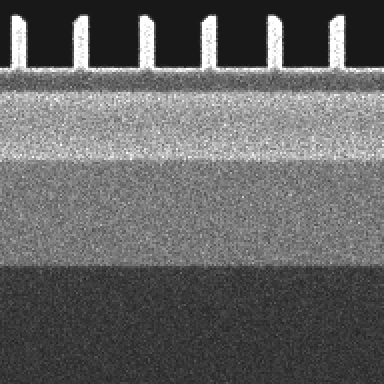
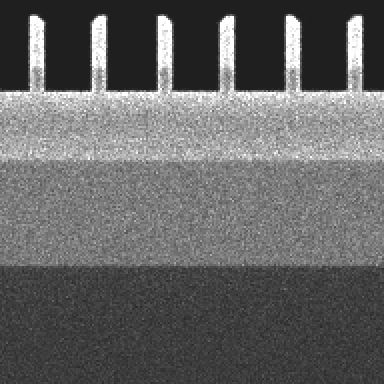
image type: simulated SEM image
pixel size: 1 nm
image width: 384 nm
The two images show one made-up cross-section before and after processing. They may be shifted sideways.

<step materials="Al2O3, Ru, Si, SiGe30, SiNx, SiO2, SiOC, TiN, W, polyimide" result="removed SiNx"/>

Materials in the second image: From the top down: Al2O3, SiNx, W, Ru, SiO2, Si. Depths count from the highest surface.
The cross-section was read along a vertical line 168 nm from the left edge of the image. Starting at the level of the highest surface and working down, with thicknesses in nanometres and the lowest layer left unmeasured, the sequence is empty 4, Al2O3 48, SiNx 24, W 52, Ru 16, SiO2 106, Si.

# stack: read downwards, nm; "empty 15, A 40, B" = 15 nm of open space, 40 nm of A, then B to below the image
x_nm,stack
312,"empty 76, W 52, Ru 16, SiO2 106, Si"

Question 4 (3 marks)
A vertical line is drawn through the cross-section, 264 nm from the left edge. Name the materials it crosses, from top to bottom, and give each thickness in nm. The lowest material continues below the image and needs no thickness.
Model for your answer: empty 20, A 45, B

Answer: empty 76, W 52, Ru 16, SiO2 106, Si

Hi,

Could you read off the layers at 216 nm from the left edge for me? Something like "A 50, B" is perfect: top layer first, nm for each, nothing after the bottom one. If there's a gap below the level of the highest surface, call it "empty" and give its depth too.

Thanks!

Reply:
empty 76, W 52, Ru 16, SiO2 106, Si